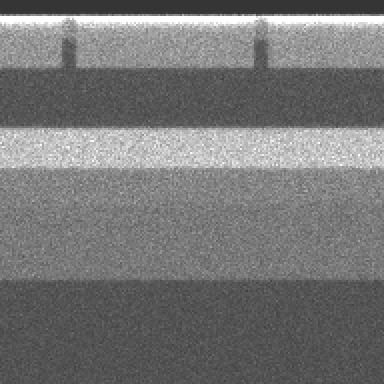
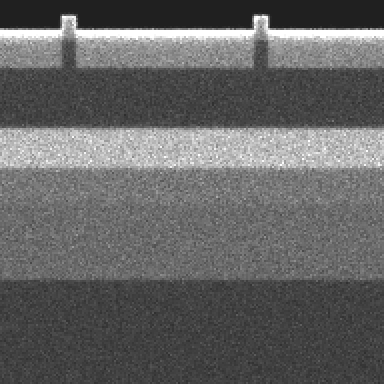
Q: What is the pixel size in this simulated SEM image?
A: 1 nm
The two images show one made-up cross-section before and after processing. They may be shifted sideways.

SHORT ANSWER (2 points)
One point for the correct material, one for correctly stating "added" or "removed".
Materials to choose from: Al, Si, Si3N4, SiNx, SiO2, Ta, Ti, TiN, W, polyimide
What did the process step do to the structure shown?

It removed SiO2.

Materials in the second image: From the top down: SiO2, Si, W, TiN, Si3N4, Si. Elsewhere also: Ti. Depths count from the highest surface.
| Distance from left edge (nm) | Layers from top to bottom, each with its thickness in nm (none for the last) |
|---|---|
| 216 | empty 14, SiO2 38, Si 60, W 40, TiN 36, Si3N4 76, Si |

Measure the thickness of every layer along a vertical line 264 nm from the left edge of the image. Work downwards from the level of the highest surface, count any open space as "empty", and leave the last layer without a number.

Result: Ti 24, Si 88, W 40, TiN 36, Si3N4 76, Si